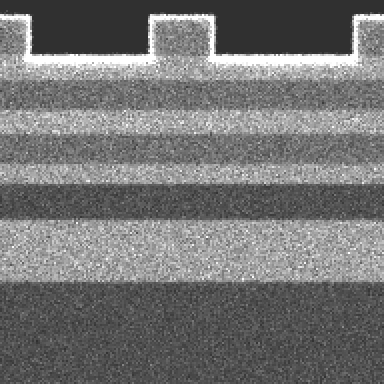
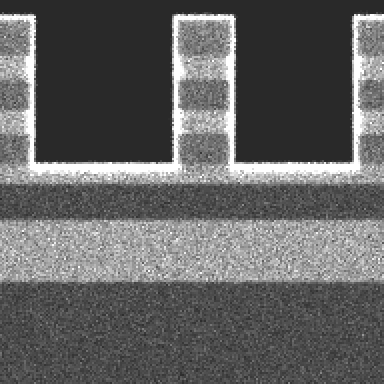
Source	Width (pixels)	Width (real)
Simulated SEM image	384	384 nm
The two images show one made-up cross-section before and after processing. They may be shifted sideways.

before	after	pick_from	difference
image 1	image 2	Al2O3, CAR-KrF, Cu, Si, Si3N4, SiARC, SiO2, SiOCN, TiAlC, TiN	Al2O3 and SiOCN removed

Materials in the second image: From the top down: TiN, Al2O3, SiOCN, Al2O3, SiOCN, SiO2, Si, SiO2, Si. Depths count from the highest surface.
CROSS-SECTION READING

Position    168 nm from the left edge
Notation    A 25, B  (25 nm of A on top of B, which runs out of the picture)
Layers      empty 148, SiO2 20, Si 36, SiO2 62, Si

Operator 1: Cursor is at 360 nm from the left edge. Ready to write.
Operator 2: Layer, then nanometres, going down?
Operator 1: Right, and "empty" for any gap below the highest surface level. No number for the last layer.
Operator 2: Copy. TiN 40, Al2O3 24, SiOCN 30, Al2O3 24, SiOCN 30, SiO2 20, Si 36, SiO2 62, Si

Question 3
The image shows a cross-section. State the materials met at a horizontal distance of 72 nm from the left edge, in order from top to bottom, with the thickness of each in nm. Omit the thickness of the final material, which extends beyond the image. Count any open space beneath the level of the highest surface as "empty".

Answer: empty 148, SiO2 20, Si 36, SiO2 62, Si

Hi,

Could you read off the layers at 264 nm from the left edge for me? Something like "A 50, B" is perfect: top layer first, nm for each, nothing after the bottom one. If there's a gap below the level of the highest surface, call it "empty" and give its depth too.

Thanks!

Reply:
empty 148, SiO2 20, Si 36, SiO2 62, Si